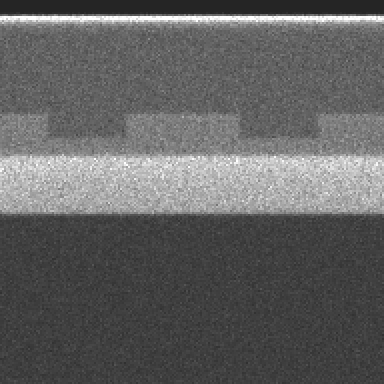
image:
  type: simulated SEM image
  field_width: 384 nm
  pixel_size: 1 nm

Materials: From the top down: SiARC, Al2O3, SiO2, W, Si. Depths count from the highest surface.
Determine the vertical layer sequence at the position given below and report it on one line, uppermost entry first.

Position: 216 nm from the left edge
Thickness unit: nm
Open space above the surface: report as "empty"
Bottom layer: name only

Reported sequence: SiARC 98, Al2O3 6, SiO2 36, W 58, Si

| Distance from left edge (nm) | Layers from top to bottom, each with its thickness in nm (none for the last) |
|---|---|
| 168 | SiARC 98, Al2O3 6, SiO2 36, W 58, Si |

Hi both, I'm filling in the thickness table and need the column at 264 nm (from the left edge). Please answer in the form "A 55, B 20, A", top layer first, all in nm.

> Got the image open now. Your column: SiARC 122, SiO2 18, W 58, Si